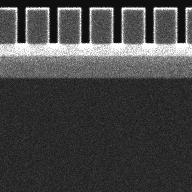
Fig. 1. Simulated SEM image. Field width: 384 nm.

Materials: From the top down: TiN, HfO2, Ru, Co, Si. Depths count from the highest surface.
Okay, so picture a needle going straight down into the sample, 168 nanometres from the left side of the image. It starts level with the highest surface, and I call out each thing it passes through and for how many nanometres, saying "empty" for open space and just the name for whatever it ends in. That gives empty 72, HfO2 24, Ru 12, Co 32, Si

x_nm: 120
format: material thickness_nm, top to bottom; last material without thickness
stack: TiN 72, HfO2 24, Ru 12, Co 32, Si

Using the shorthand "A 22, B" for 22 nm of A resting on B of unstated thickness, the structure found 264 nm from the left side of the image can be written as TiN 72, HfO2 24, Ru 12, Co 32, Si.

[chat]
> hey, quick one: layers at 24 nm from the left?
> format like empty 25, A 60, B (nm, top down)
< TiN 72, HfO2 24, Ru 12, Co 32, Si